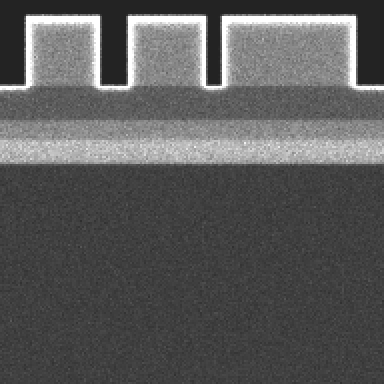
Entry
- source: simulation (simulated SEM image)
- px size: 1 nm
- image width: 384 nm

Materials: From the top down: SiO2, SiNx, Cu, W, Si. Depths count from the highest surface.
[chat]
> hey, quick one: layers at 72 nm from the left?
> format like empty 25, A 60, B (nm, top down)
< SiO2 70, SiNx 34, Cu 20, W 24, Si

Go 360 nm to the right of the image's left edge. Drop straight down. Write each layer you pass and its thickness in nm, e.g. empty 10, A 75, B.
empty 70, SiNx 34, Cu 20, W 24, Si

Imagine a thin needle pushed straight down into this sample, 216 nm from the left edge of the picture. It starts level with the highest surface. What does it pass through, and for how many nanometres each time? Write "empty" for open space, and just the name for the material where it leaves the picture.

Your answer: empty 70, SiNx 34, Cu 20, W 24, Si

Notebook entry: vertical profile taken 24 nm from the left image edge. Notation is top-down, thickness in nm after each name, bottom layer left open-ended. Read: empty 70, SiNx 34, Cu 20, W 24, Si